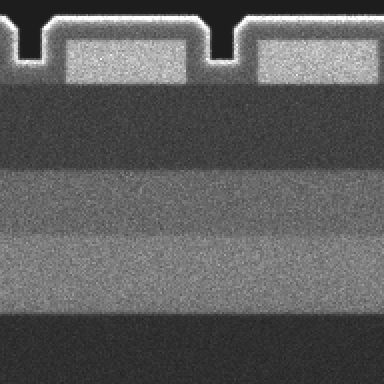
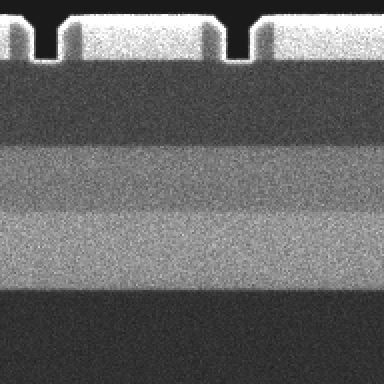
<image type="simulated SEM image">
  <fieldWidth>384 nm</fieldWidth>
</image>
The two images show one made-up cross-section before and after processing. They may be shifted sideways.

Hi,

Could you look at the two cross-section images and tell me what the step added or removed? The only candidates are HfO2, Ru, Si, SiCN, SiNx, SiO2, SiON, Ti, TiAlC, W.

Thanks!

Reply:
removed SiO2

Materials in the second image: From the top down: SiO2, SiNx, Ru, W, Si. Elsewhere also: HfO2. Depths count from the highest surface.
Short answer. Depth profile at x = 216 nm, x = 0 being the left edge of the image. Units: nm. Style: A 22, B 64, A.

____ empty 4, SiO2 40, SiNx 86, Ru 66, W 78, Si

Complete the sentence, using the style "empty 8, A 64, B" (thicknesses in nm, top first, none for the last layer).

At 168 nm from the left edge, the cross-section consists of HfO2 44, SiNx 86, Ru 66, W 78, Si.